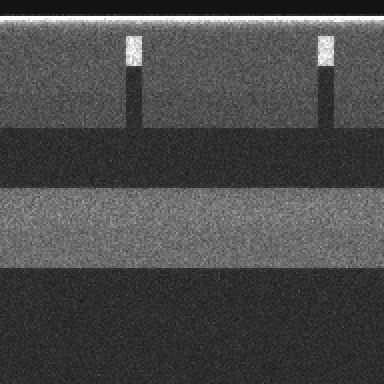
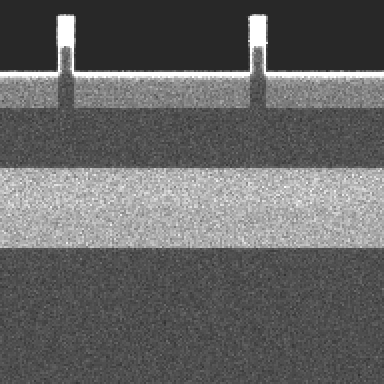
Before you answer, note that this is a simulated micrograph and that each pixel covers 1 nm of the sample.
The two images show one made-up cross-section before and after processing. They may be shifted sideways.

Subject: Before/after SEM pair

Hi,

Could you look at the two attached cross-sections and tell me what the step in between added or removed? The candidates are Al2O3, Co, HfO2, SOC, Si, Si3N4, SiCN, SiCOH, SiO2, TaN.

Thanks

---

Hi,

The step removed SOC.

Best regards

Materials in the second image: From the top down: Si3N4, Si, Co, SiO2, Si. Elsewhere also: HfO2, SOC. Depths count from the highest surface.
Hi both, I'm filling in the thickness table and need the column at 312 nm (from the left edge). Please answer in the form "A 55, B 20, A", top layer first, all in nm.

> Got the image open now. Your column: empty 56, Si3N4 36, Si 60, Co 40, SiO2 40, Si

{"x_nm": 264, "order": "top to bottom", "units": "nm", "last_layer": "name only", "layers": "HfO2 30, Si 122, Co 40, SiO2 40, Si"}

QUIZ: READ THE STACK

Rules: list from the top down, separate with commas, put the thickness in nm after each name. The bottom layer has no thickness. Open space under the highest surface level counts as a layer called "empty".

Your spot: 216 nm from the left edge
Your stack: empty 56, Si3N4 36, Si 60, Co 40, SiO2 40, Si